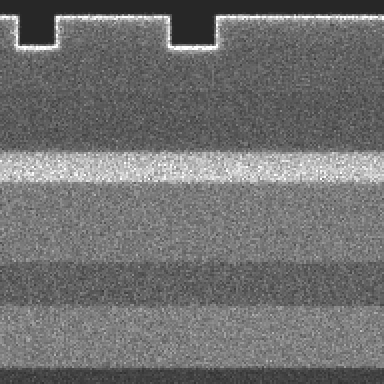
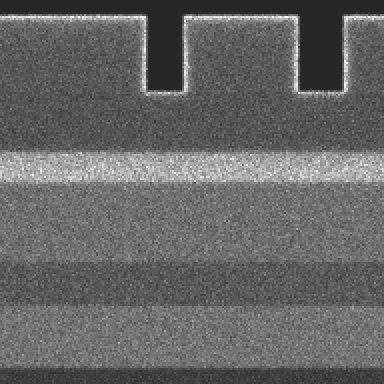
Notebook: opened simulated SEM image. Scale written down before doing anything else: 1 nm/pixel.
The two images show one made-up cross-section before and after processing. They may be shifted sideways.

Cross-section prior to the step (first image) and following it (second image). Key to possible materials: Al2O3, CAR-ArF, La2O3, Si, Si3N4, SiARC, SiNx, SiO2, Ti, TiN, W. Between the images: Si3N4 was removed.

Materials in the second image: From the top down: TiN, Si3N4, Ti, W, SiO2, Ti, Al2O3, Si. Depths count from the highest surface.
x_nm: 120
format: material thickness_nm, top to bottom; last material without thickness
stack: TiN 30, Si3N4 46, Ti 60, W 30, SiO2 80, Ti 44, Al2O3 62, Si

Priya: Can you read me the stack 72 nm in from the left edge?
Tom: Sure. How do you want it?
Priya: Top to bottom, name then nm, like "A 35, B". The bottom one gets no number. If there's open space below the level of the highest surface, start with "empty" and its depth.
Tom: TiN 30, Si3N4 46, Ti 60, W 30, SiO2 80, Ti 44, Al2O3 62, Si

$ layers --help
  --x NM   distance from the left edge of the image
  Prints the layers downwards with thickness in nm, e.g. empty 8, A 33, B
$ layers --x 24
TiN 30, Si3N4 46, Ti 60, W 30, SiO2 80, Ti 44, Al2O3 62, Si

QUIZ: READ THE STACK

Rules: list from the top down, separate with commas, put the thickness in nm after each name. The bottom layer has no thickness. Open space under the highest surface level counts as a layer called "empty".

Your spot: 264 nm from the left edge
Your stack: TiN 30, Si3N4 46, Ti 60, W 30, SiO2 80, Ti 44, Al2O3 62, Si